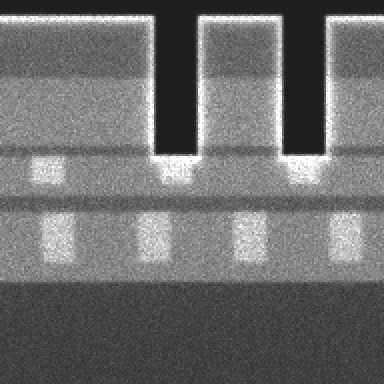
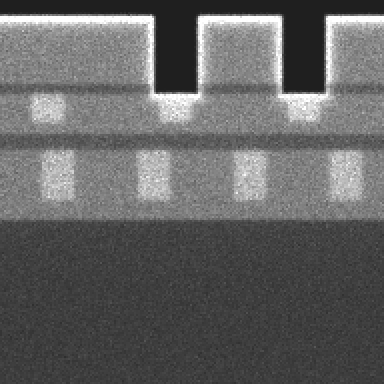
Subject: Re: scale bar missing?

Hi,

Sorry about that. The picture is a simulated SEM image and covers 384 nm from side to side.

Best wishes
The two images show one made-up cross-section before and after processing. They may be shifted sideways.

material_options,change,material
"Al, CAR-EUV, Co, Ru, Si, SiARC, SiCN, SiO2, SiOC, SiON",removed,SiARC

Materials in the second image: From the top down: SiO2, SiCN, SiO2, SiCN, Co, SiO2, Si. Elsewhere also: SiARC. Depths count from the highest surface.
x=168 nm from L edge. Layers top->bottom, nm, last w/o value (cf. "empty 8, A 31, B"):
empty 78, Co 28, SiO2 12, SiCN 16, Co 50, SiO2 20, Si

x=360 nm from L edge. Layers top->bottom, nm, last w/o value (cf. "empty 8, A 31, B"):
SiO2 68, SiCN 10, SiO2 40, SiCN 16, Co 50, SiO2 20, Si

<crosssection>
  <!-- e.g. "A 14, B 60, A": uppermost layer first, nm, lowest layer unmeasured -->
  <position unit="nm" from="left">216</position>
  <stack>SiO2 68, SiCN 10, SiO2 40, SiCN 16, SiO2 70, Si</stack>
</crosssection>